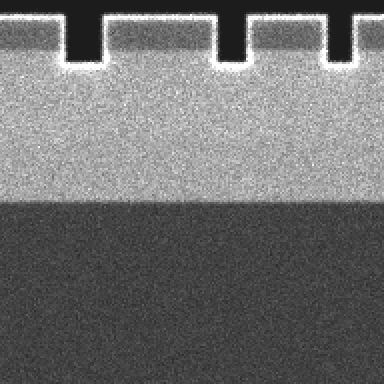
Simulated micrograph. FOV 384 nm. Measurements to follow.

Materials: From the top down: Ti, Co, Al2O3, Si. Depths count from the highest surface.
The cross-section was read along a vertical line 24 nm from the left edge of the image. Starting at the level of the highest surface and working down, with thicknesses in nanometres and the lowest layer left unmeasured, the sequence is Ti 34, Co 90, Al2O3 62, Si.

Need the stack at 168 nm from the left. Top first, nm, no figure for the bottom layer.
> Ti 34, Co 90, Al2O3 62, Si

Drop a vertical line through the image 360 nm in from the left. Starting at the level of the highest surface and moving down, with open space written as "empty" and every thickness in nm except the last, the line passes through Ti 34, Co 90, Al2O3 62, Si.